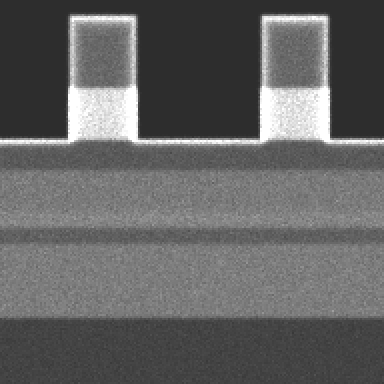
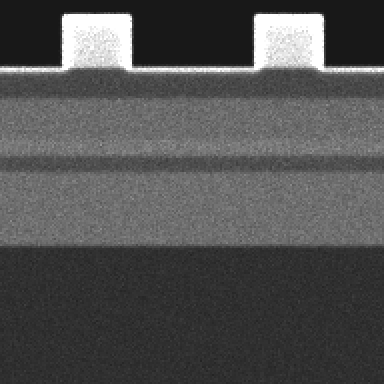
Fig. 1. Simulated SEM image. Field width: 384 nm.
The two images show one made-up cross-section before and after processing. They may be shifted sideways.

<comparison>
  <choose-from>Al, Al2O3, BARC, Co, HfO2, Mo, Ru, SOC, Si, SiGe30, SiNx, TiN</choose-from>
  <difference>SOC removed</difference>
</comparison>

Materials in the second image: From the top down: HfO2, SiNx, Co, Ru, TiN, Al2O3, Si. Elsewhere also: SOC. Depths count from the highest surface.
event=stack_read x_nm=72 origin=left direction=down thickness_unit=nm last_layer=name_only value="HfO2 52, SiNx 30, Co 42, Ru 16, TiN 16, Al2O3 74, Si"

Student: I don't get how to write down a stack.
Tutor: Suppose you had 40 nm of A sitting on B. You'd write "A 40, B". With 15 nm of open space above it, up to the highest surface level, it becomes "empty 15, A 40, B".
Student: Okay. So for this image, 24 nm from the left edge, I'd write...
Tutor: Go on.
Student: empty 52, SiNx 30, Co 42, Ru 16, TiN 16, Al2O3 74, Si